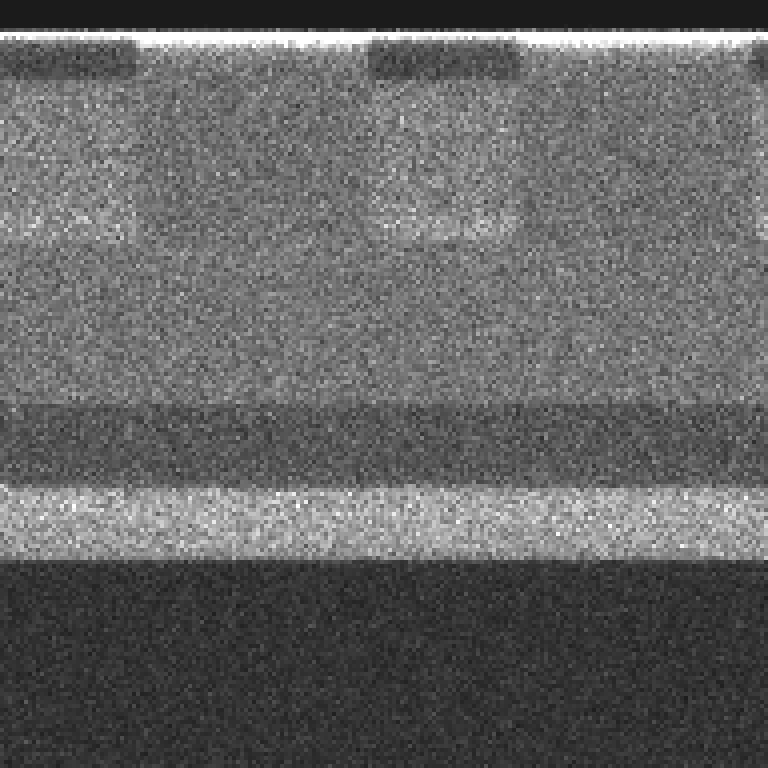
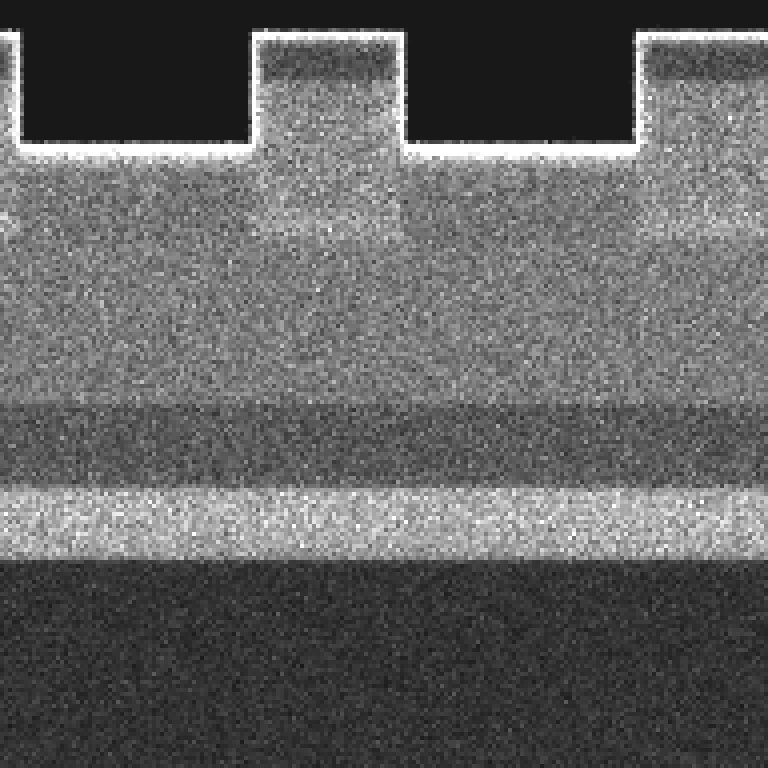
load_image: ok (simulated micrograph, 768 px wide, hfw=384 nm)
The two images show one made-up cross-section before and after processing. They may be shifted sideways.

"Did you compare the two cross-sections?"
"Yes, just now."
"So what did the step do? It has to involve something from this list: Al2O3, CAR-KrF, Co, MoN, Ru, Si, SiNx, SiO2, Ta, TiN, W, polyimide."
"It removed SiO2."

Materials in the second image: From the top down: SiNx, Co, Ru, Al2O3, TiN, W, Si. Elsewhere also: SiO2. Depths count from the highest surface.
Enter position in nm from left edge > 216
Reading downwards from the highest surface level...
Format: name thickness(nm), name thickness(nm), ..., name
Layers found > empty 56, SiO2 48, Al2O3 82, TiN 42, W 36, Si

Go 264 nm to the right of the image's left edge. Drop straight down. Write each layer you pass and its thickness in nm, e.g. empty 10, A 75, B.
empty 56, SiO2 48, Al2O3 82, TiN 42, W 36, Si